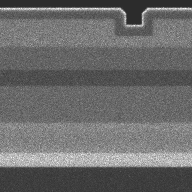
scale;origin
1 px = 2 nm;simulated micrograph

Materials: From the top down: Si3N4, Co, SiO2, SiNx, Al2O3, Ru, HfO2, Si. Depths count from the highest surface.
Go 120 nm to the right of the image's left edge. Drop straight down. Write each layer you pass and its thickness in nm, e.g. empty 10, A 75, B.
Si3N4 22, Co 56, SiO2 46, SiNx 32, Al2O3 74, Ru 60, HfO2 28, Si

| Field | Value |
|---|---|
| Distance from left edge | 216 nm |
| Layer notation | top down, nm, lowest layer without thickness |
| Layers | Si3N4 22, Co 56, SiO2 46, SiNx 32, Al2O3 74, Ru 60, HfO2 28, Si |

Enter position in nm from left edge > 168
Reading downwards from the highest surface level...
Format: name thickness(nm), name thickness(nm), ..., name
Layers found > Si3N4 22, Co 56, SiO2 46, SiNx 32, Al2O3 74, Ru 60, HfO2 28, Si